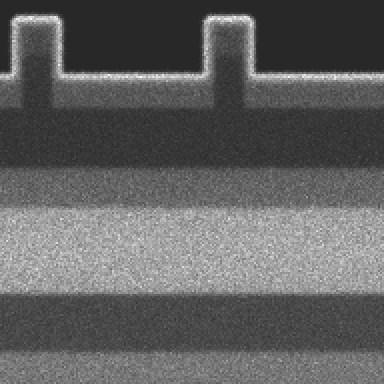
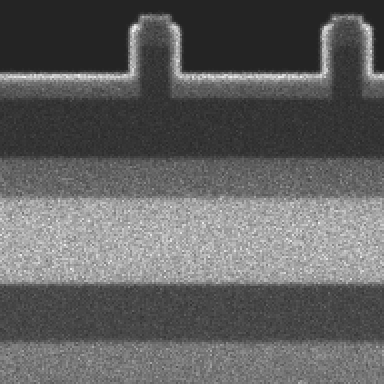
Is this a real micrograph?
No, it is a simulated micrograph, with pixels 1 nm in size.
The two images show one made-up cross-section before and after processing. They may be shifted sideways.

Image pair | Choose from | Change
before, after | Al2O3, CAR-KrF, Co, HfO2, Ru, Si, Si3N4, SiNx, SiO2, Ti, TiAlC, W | Al2O3 (removed)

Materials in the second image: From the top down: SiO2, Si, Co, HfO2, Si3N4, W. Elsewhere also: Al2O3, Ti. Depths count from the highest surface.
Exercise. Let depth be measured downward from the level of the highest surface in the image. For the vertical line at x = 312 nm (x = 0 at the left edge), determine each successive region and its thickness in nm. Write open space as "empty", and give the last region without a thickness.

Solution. empty 58, SiO2 24, Si 60, Co 40, HfO2 86, Si3N4 58, W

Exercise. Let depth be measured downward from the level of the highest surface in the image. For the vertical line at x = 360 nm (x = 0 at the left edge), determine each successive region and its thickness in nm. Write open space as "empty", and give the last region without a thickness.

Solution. Ti 30, Si 112, Co 40, HfO2 86, Si3N4 58, W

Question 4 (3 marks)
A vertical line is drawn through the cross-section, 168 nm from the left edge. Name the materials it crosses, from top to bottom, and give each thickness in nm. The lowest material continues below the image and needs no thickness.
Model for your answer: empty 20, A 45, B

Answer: Ti 30, Si 112, Co 40, HfO2 86, Si3N4 58, W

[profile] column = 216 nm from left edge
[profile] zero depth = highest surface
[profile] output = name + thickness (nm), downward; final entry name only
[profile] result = empty 58, SiO2 24, Si 60, Co 40, HfO2 86, Si3N4 58, W